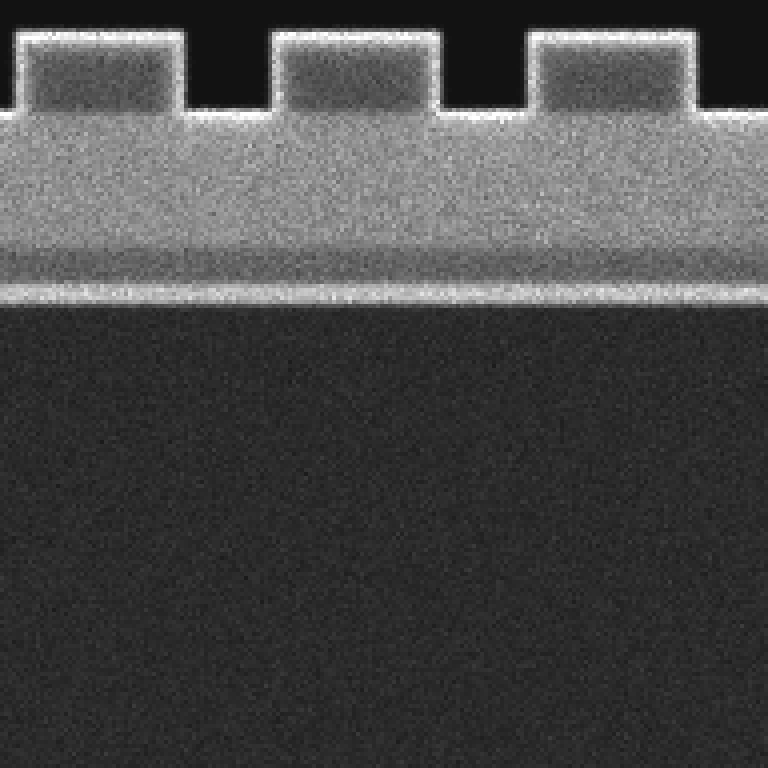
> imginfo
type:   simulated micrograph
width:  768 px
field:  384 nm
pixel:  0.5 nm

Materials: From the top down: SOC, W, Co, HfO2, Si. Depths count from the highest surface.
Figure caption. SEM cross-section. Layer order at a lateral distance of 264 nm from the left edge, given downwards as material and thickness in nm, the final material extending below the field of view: SOC 40, W 68, Co 18, HfO2 10, Si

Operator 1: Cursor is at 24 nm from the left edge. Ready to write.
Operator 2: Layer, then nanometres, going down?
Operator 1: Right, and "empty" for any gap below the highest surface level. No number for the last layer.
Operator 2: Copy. SOC 40, W 68, Co 18, HfO2 10, Si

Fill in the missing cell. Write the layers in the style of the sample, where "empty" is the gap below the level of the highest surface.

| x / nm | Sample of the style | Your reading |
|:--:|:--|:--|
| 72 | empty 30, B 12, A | SOC 40, W 68, Co 18, HfO2 10, Si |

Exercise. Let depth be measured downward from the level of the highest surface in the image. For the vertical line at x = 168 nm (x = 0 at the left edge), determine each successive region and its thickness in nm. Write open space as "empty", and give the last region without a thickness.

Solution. SOC 40, W 68, Co 18, HfO2 10, Si